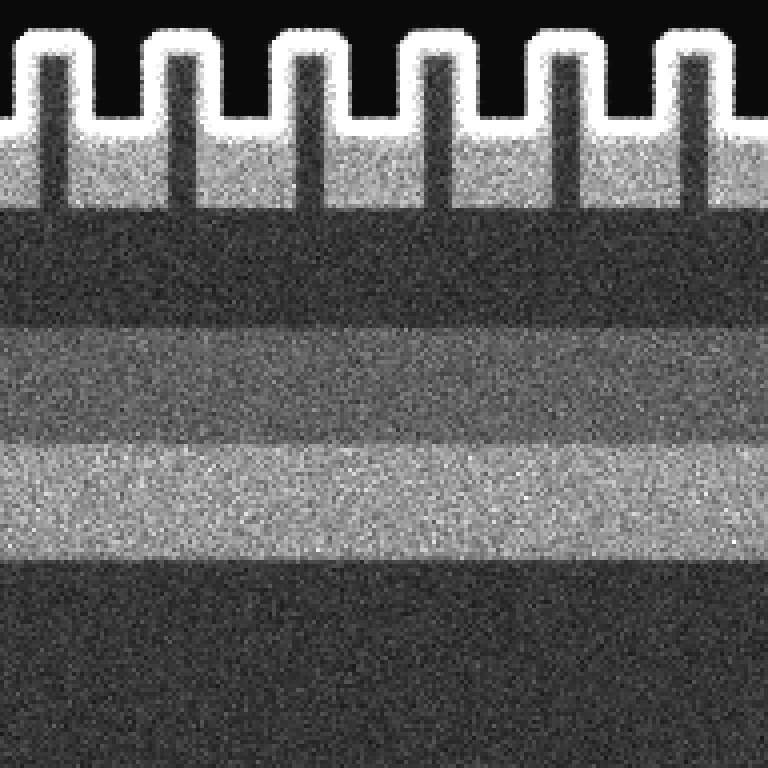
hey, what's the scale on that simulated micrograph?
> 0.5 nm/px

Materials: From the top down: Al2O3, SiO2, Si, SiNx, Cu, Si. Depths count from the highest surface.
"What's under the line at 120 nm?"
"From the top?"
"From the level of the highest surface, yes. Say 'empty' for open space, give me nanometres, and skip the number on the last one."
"empty 44, Al2O3 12, SiO2 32, Si 60, SiNx 58, Cu 58, Si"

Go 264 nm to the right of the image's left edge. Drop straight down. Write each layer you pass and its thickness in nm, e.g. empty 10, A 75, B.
empty 6, Al2O3 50, SiO2 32, Si 60, SiNx 58, Cu 58, Si